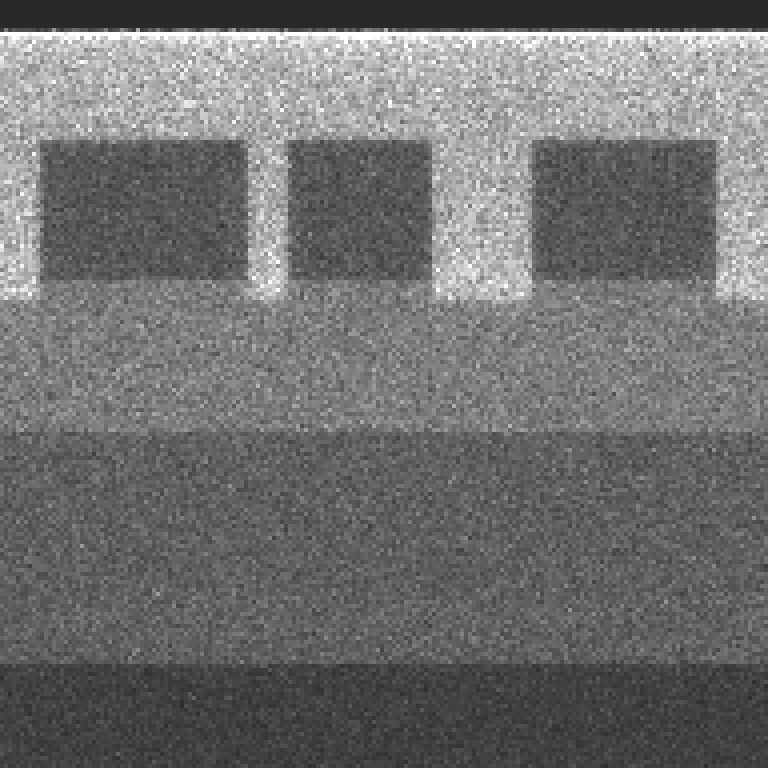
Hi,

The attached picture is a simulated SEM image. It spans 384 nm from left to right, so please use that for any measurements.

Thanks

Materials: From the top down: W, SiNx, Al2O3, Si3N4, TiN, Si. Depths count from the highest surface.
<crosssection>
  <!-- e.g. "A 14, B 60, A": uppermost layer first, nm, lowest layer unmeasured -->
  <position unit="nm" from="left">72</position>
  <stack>W 54, SiNx 70, Al2O3 76, Si3N4 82, TiN 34, Si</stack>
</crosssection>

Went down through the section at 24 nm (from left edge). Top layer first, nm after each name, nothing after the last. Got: W 54, SiNx 70, Al2O3 76, Si3N4 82, TiN 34, Si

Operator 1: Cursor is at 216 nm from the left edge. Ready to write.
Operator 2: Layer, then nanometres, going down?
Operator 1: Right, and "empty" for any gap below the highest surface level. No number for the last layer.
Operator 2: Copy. W 134, Al2O3 66, Si3N4 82, TiN 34, Si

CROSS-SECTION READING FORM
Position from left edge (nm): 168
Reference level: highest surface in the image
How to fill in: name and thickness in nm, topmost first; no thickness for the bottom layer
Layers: W 54, SiNx 70, Al2O3 76, Si3N4 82, TiN 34, Si